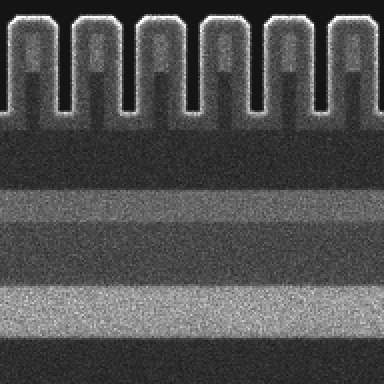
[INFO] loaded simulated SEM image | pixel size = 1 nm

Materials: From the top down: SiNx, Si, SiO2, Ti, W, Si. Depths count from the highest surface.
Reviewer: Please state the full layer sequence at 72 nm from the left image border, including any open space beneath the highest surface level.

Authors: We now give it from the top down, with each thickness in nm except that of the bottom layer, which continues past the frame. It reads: empty 8, SiNx 106, Si 60, SiO2 32, Ti 64, W 52, Si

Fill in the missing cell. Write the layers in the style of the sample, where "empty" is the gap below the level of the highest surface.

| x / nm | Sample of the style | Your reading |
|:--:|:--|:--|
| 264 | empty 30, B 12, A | empty 8, SiNx 106, Si 60, SiO2 32, Ti 64, W 52, Si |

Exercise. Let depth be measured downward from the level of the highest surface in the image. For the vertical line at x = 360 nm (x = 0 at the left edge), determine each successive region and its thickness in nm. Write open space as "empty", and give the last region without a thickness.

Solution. SiNx 114, Si 60, SiO2 32, Ti 64, W 52, Si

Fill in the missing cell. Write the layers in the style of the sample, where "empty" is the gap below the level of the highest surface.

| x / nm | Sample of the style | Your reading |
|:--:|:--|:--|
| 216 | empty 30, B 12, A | SiNx 114, Si 60, SiO2 32, Ti 64, W 52, Si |